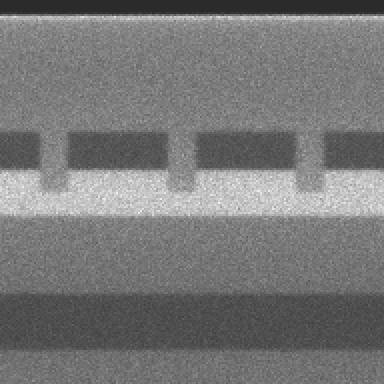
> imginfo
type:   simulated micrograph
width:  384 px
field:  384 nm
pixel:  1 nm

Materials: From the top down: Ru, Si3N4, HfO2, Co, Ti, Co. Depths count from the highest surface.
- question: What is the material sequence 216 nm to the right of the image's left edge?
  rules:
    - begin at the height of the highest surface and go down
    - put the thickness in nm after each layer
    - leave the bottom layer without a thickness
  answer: Ru 116, Si3N4 38, HfO2 46, Co 78, Ti 56, Co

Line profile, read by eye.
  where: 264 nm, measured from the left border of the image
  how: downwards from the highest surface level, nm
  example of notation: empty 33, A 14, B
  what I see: Ru 116, Si3N4 38, HfO2 46, Co 78, Ti 56, Co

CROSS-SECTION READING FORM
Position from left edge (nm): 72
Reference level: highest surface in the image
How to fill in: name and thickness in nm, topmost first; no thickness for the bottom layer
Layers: Ru 116, Si3N4 38, HfO2 46, Co 78, Ti 56, Co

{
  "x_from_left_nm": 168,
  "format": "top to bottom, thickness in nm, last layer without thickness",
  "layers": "Ru 176, HfO2 24, Co 78, Ti 56, Co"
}